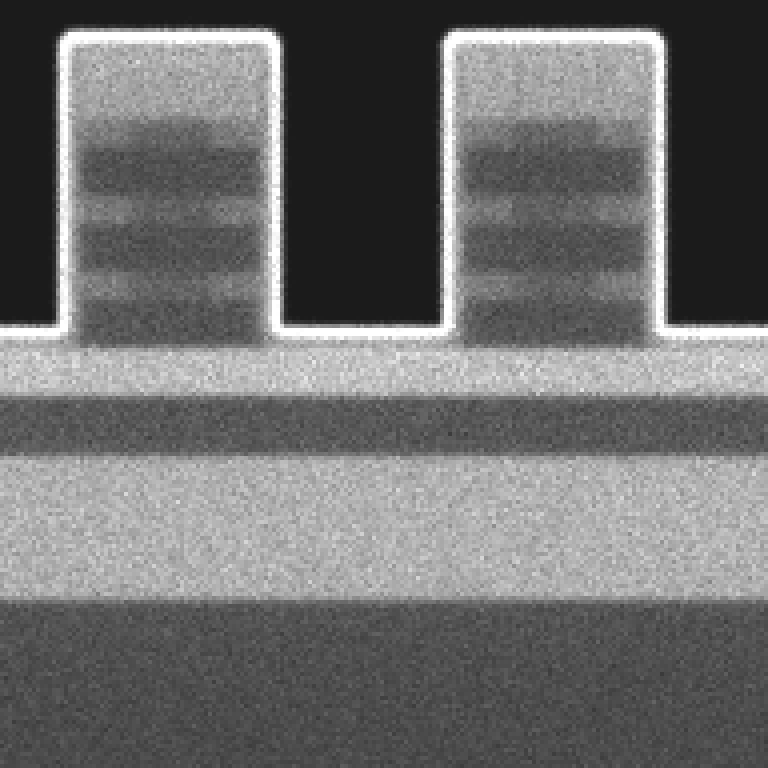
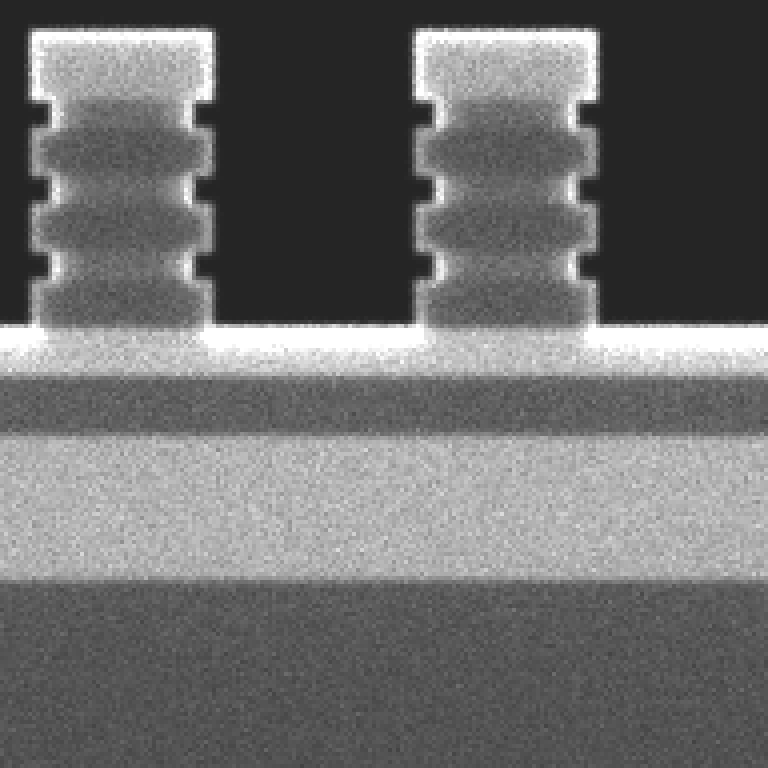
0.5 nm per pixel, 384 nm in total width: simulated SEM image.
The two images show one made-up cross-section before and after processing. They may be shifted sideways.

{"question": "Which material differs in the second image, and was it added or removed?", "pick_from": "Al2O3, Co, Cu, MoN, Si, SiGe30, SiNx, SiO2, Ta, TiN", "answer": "SiNx, removed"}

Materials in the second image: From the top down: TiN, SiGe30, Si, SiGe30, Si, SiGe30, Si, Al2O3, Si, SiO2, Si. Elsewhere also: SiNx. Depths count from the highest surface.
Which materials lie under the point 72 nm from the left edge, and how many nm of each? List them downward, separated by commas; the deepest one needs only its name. TiN 34, SiGe30 14, Si 24, SiGe30 14, Si 24, SiGe30 14, Si 24, Al2O3 24, Si 30, SiO2 72, Si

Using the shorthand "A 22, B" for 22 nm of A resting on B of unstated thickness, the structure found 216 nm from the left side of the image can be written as TiN 34, empty 14, Si 24, empty 14, Si 24, empty 14, Si 24, Al2O3 24, Si 30, SiO2 72, Si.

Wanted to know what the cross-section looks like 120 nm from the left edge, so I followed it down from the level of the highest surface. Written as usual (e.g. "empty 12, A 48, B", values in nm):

empty 148, Al2O3 24, Si 30, SiO2 72, Si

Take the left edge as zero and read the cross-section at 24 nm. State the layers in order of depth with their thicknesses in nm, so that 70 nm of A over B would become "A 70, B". TiN 34, empty 14, Si 24, empty 14, Si 24, empty 14, Si 24, Al2O3 24, Si 30, SiO2 72, Si